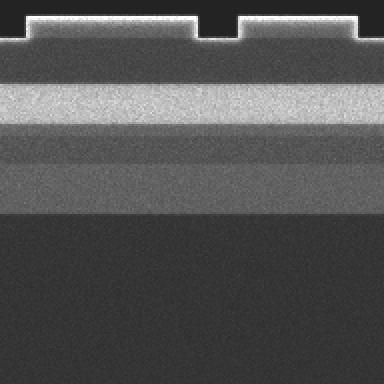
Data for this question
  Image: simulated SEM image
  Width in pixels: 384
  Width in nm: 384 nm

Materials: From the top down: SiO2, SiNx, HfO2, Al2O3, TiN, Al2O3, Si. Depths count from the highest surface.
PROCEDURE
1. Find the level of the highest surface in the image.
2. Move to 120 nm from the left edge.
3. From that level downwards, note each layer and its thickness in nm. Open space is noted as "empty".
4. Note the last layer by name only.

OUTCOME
SiO2 22, SiNx 46, HfO2 40, Al2O3 12, TiN 28, Al2O3 50, Si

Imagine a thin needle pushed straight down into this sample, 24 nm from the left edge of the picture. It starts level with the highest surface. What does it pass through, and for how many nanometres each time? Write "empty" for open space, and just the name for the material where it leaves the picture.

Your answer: empty 22, SiNx 46, HfO2 40, Al2O3 12, TiN 28, Al2O3 50, Si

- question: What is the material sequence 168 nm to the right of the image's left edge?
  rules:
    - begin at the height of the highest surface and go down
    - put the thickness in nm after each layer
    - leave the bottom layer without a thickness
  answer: SiO2 22, SiNx 46, HfO2 40, Al2O3 12, TiN 28, Al2O3 50, Si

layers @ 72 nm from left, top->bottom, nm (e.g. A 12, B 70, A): SiO2 22, SiNx 46, HfO2 40, Al2O3 12, TiN 28, Al2O3 50, Si